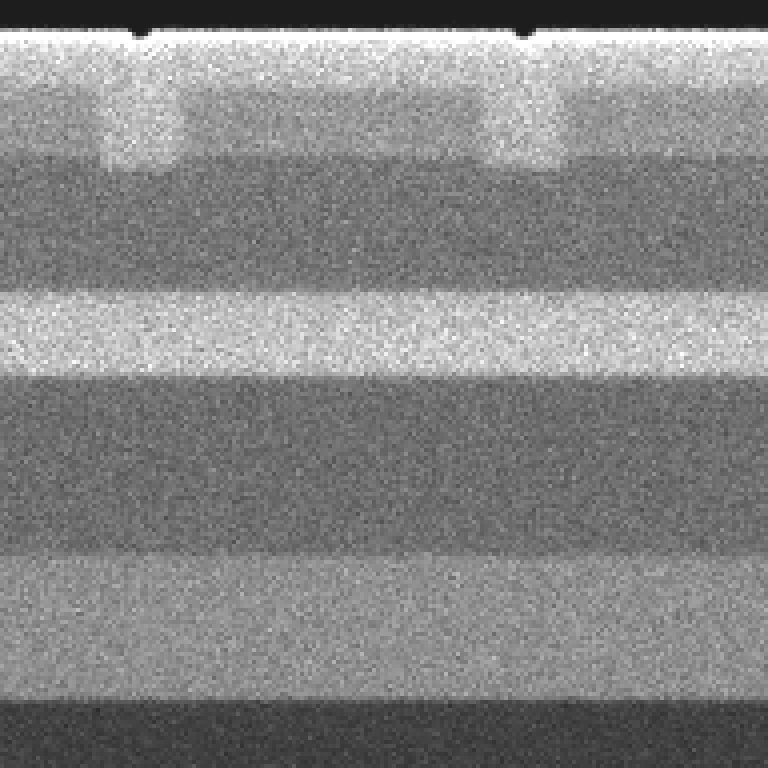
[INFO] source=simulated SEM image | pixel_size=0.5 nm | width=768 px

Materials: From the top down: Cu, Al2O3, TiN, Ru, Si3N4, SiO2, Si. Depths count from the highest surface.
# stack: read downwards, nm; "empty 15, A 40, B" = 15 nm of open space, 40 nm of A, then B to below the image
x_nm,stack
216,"Cu 28, Al2O3 34, TiN 68, Ru 42, Si3N4 90, SiO2 72, Si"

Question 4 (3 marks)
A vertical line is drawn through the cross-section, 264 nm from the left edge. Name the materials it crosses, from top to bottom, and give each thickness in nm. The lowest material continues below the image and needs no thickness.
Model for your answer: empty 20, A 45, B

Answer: empty 4, Cu 64, TiN 62, Ru 42, Si3N4 90, SiO2 72, Si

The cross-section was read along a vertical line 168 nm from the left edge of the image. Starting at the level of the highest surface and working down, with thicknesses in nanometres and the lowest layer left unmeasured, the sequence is Cu 28, Al2O3 34, TiN 68, Ru 42, Si3N4 90, SiO2 72, Si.